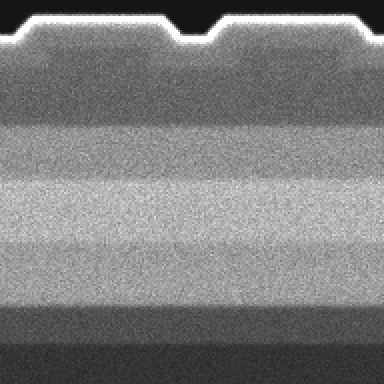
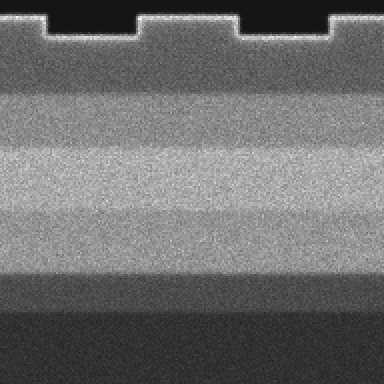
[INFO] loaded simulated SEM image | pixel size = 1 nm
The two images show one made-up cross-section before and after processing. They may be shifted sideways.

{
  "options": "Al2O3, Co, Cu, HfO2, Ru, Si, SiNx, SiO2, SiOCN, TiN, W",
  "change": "removed",
  "material": "SiO2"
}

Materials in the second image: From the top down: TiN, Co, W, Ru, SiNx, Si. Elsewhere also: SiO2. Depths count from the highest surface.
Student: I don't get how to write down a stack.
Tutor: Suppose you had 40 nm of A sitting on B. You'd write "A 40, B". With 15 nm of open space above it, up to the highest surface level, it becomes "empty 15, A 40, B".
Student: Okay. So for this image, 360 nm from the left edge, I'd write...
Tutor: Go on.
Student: TiN 78, Co 54, W 62, Ru 64, SiNx 38, Si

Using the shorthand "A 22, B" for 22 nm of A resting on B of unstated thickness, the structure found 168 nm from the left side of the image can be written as TiN 78, Co 54, W 62, Ru 64, SiNx 38, Si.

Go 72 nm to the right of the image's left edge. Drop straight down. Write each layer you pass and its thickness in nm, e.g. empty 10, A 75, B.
empty 20, TiN 58, Co 54, W 62, Ru 64, SiNx 38, Si